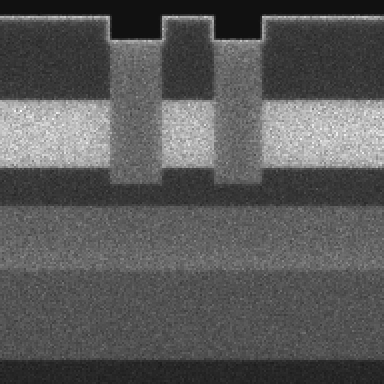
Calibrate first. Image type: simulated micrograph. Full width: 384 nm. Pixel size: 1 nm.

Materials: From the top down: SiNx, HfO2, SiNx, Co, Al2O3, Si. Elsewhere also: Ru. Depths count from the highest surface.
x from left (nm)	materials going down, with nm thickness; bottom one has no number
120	empty 24, Ru 144, SiNx 22, Co 64, Al2O3 90, Si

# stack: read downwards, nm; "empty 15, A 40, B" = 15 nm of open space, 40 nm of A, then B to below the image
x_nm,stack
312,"SiNx 84, HfO2 68, SiNx 38, Co 64, Al2O3 90, Si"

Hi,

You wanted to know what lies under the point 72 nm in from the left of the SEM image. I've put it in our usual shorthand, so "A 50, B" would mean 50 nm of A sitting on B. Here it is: SiNx 84, HfO2 68, SiNx 38, Co 64, Al2O3 90, Si